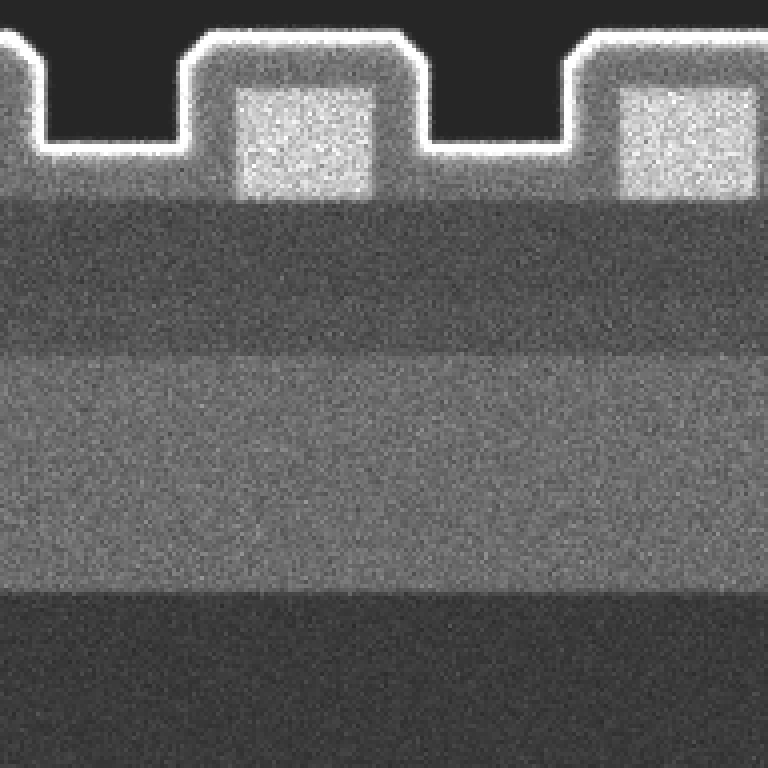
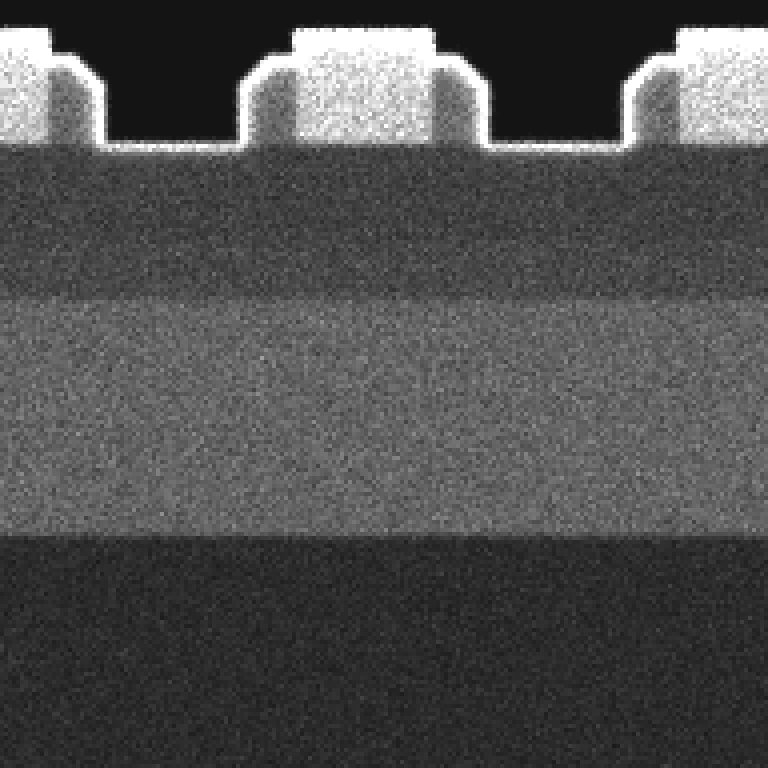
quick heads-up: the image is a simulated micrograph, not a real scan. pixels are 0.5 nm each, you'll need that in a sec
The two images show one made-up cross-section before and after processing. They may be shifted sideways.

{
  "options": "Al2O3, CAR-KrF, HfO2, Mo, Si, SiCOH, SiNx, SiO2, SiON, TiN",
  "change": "removed",
  "material": "Al2O3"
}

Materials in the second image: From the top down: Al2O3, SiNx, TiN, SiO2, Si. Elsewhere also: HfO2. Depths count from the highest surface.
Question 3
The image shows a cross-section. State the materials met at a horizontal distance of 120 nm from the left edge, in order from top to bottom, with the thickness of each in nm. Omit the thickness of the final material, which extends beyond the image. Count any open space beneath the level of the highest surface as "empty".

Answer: empty 26, Al2O3 30, SiNx 48, TiN 30, SiO2 118, Si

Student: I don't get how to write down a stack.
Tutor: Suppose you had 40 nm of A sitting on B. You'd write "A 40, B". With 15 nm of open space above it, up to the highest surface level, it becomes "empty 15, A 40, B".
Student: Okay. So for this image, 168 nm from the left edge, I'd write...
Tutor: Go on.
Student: HfO2 56, SiNx 48, TiN 30, SiO2 118, Si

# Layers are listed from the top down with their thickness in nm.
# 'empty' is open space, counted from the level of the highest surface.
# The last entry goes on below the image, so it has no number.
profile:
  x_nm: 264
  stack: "empty 56, SiNx 48, TiN 30, SiO2 118, Si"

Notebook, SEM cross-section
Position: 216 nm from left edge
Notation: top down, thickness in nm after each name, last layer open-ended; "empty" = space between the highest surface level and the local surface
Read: empty 12, Al2O3 44, SiNx 48, TiN 30, SiO2 118, Si